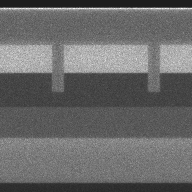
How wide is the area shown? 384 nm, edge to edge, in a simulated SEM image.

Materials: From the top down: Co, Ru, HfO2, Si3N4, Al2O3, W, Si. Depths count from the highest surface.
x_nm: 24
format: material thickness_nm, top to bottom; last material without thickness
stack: Co 66, Ru 8, HfO2 56, Si3N4 68, Al2O3 62, W 90, Si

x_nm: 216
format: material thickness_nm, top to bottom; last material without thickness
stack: Co 66, Ru 8, HfO2 56, Si3N4 68, Al2O3 62, W 90, Si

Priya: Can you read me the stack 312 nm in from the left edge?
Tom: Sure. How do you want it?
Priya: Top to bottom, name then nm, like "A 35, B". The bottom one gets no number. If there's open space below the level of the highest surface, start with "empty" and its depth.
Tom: Co 70, Ru 98, Si3N4 30, Al2O3 62, W 90, Si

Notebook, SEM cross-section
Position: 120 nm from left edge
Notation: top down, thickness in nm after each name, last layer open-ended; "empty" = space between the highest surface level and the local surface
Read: Co 70, Ru 98, Si3N4 30, Al2O3 62, W 90, Si